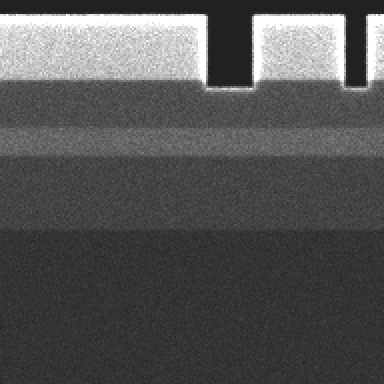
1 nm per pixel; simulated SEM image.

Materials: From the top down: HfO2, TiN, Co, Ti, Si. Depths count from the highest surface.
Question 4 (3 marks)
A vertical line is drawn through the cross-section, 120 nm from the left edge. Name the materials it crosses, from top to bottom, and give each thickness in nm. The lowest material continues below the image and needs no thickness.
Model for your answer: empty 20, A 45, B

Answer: HfO2 64, TiN 48, Co 28, Ti 74, Si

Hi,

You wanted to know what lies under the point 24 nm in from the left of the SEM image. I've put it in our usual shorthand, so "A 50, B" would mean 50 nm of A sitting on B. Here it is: HfO2 64, TiN 48, Co 28, Ti 74, Si